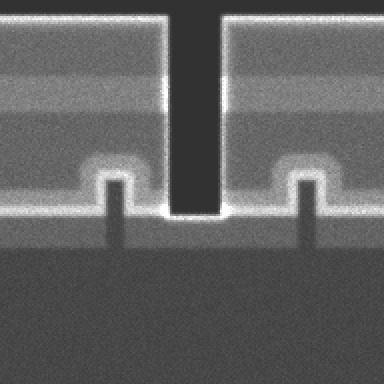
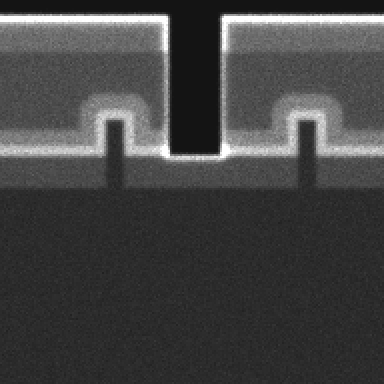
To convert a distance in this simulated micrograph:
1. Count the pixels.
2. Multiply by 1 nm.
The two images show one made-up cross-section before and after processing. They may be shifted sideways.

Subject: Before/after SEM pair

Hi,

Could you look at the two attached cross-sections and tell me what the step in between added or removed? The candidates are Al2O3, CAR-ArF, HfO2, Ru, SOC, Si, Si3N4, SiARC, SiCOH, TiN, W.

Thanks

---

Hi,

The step removed SOC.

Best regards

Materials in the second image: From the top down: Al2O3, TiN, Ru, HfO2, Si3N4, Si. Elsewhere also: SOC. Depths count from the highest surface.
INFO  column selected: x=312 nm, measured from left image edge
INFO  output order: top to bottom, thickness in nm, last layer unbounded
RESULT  Al2O3 36, TiN 42, Ru 16, HfO2 10, Si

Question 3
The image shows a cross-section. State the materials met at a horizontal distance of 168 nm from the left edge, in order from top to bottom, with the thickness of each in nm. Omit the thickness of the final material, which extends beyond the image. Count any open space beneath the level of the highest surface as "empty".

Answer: empty 140, Si3N4 32, Si